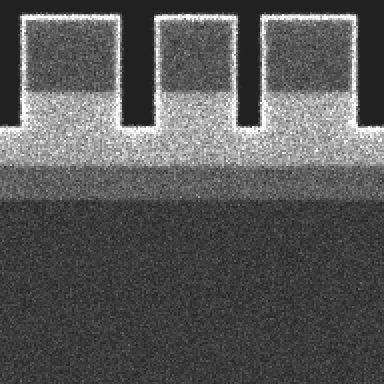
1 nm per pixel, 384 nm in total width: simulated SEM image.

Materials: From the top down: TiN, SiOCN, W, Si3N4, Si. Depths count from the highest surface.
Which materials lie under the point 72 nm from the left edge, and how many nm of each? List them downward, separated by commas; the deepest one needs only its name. TiN 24, SiOCN 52, W 74, Si3N4 34, Si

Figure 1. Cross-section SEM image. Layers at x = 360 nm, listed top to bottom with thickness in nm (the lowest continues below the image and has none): empty 112, W 38, Si3N4 34, Si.